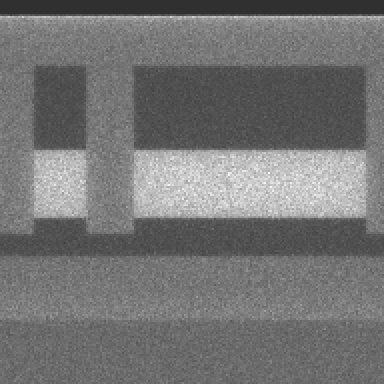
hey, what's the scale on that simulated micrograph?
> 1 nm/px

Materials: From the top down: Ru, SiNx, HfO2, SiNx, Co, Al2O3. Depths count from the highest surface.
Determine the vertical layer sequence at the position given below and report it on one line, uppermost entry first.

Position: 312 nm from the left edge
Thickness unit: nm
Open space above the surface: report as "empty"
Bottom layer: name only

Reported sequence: Ru 50, SiNx 84, HfO2 68, SiNx 38, Co 64, Al2O3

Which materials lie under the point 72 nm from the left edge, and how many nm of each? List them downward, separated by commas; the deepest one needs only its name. Ru 50, SiNx 84, HfO2 68, SiNx 38, Co 64, Al2O3